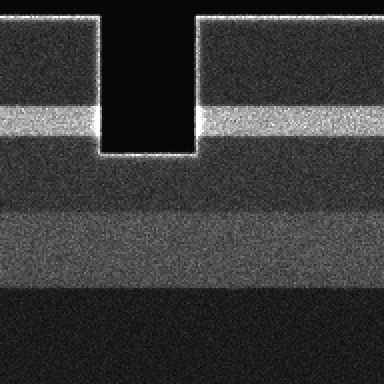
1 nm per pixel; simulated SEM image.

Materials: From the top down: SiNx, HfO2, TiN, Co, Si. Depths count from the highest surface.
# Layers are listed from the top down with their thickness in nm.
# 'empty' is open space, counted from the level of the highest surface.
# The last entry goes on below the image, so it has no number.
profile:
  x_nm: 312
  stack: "SiNx 90, HfO2 30, TiN 76, Co 76, Si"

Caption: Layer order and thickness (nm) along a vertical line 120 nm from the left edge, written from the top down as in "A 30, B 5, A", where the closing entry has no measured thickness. empty 138, TiN 58, Co 76, Si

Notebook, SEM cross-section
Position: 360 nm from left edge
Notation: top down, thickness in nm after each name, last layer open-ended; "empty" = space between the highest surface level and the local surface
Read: SiNx 90, HfO2 30, TiN 76, Co 76, Si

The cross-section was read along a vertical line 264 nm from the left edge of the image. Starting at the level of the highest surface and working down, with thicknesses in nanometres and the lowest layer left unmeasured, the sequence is SiNx 90, HfO2 30, TiN 76, Co 76, Si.